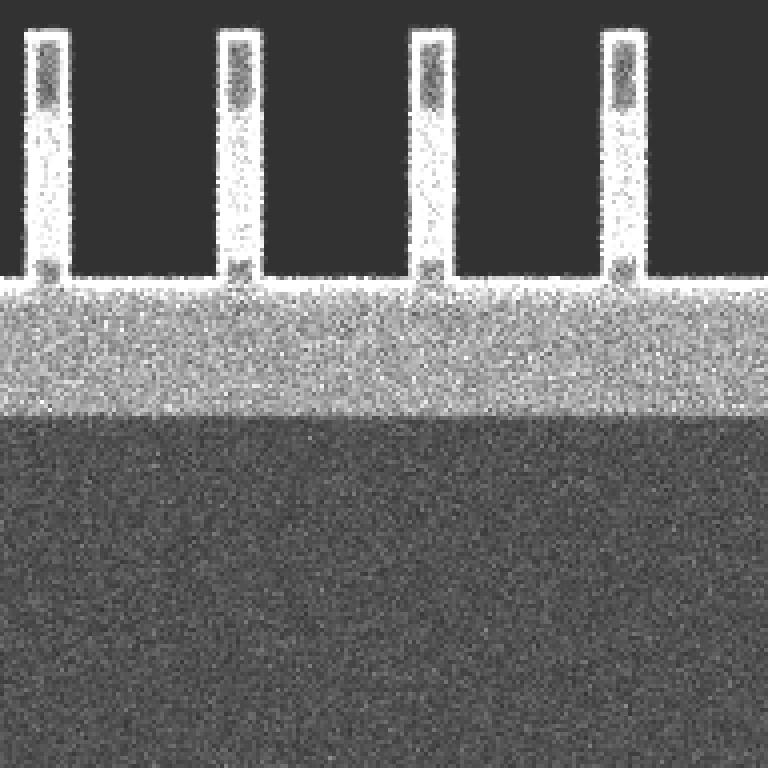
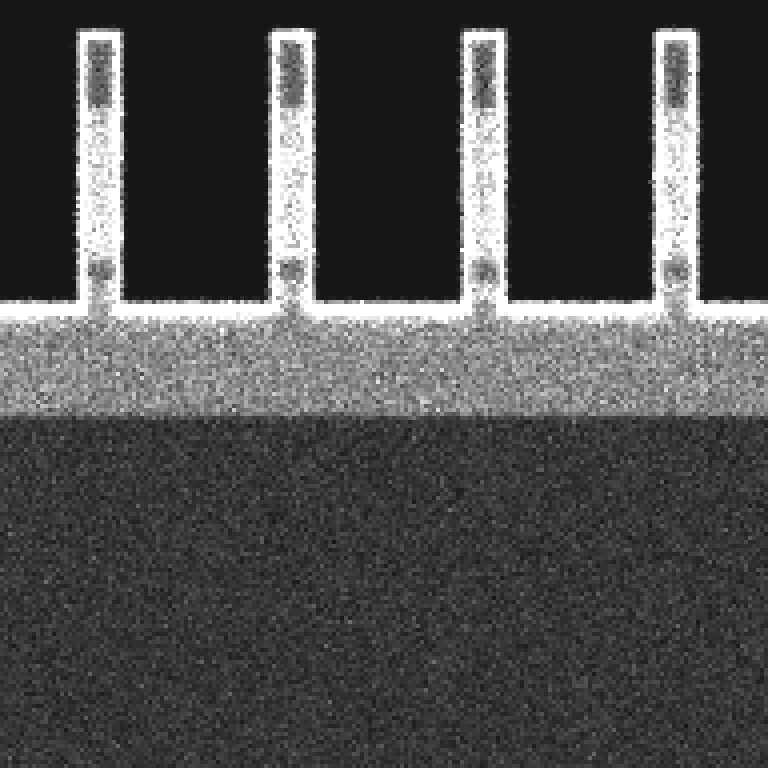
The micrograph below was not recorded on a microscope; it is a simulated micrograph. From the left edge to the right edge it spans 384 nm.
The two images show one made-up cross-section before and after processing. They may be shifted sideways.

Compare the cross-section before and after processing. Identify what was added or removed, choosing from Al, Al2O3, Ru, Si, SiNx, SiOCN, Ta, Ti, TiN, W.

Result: Ru removed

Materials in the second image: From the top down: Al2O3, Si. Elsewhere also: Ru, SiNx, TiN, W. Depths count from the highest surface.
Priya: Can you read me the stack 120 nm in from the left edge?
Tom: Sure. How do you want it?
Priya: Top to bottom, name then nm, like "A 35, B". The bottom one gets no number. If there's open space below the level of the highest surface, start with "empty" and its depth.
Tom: empty 136, Al2O3 56, Si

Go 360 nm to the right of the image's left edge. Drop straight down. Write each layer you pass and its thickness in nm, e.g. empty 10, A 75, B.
empty 136, Al2O3 56, Si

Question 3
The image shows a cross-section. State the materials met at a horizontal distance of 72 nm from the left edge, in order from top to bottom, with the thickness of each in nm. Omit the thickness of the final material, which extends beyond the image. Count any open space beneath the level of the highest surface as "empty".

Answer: empty 136, Al2O3 56, Si